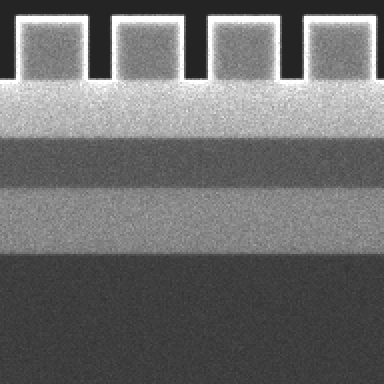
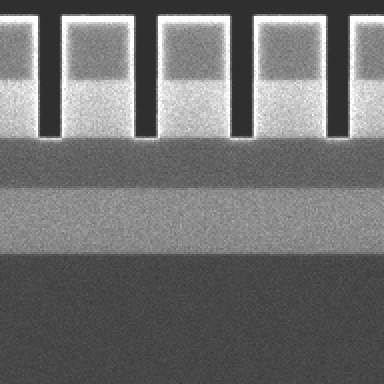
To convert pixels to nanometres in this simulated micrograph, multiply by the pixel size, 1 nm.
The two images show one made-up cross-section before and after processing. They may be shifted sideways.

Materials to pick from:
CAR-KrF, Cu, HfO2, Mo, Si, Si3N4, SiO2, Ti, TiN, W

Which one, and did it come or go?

W - removed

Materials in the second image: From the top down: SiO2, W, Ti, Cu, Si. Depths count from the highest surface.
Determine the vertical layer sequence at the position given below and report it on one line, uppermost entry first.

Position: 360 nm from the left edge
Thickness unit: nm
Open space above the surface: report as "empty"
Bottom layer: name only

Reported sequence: SiO2 64, W 58, Ti 50, Cu 66, Si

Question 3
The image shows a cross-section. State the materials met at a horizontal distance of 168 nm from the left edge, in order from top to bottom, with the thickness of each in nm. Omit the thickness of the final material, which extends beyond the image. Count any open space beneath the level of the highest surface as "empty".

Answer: SiO2 64, W 58, Ti 50, Cu 66, Si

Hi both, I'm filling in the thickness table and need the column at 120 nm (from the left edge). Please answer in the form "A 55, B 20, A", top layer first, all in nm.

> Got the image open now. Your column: SiO2 64, W 58, Ti 50, Cu 66, Si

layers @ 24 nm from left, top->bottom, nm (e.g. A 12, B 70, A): SiO2 64, W 58, Ti 50, Cu 66, Si